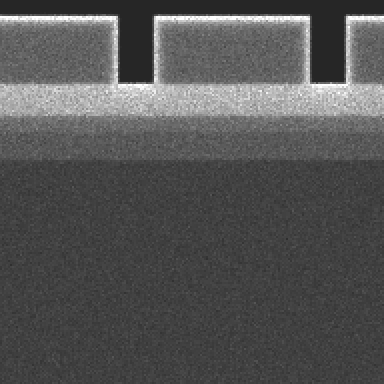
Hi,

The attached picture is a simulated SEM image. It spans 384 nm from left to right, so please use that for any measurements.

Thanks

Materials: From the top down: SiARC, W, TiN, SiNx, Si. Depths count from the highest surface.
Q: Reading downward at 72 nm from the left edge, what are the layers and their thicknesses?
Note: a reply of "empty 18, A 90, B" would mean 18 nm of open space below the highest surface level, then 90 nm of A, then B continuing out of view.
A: SiARC 68, W 32, TiN 16, SiNx 28, Si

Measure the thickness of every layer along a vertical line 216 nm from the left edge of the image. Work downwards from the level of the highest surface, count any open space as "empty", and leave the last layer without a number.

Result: SiARC 68, W 32, TiN 16, SiNx 28, Si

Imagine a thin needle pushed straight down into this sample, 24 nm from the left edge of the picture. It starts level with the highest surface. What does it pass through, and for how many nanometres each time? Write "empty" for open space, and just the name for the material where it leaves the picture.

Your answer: SiARC 68, W 32, TiN 16, SiNx 28, Si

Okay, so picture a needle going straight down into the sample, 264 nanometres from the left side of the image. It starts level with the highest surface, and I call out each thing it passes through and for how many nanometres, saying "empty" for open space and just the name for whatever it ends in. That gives SiARC 68, W 32, TiN 16, SiNx 28, Si